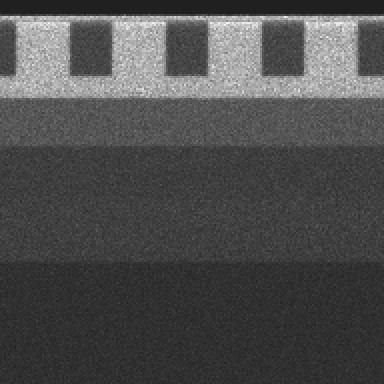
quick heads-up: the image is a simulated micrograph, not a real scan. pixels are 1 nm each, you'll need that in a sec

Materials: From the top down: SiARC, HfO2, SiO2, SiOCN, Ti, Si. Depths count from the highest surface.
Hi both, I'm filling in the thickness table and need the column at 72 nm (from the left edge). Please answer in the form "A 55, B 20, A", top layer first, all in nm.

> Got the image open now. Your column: SiARC 60, HfO2 22, SiO2 48, SiOCN 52, Ti 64, Si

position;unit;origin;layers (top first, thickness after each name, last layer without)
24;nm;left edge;SiARC 6, HfO2 76, SiO2 48, SiOCN 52, Ti 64, Si